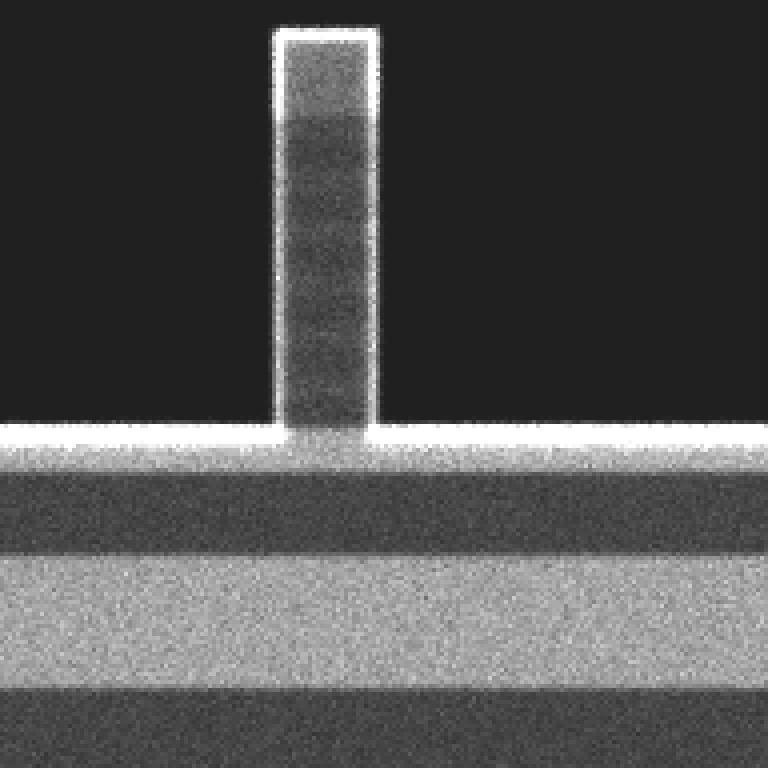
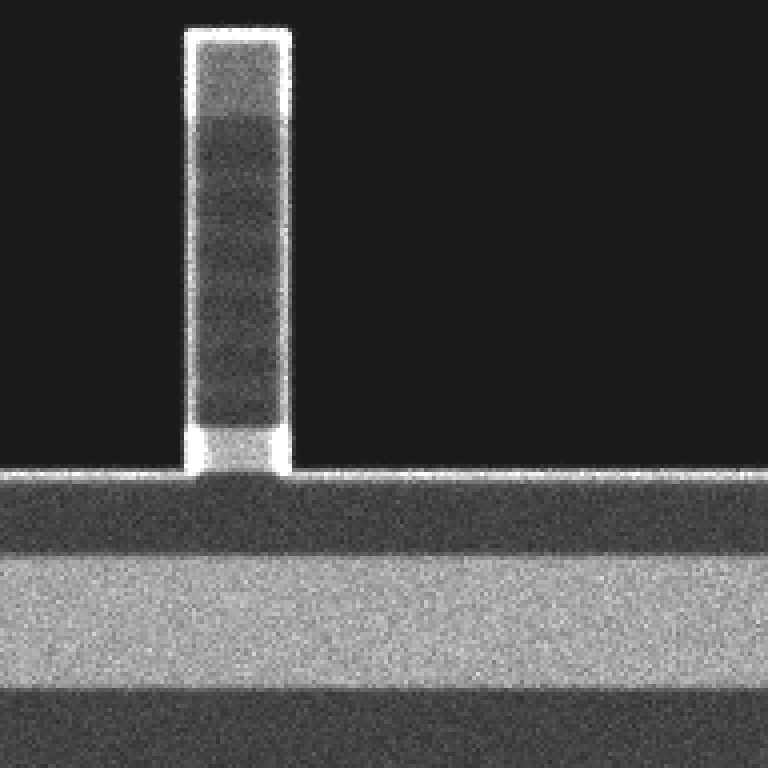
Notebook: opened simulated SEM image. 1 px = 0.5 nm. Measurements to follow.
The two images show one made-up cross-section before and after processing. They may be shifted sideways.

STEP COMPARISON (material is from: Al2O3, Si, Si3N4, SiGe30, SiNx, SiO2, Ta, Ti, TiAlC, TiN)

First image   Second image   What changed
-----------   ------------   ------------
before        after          Al2O3, removed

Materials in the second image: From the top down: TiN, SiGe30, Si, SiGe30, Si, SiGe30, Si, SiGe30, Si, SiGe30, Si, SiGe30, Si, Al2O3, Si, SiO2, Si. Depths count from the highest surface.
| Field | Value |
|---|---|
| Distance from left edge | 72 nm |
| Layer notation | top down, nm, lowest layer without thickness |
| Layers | empty 220, Si 42, SiO2 66, Si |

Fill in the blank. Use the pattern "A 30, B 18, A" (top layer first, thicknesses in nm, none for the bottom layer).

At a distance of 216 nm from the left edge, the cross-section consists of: empty 220, Si 42, SiO2 66, Si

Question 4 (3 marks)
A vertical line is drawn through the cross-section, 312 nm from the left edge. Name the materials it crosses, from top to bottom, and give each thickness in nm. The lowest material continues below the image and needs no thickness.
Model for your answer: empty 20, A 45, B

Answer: empty 220, Si 42, SiO2 66, Si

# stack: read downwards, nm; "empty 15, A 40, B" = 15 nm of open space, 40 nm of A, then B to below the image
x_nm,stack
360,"empty 220, Si 42, SiO2 66, Si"